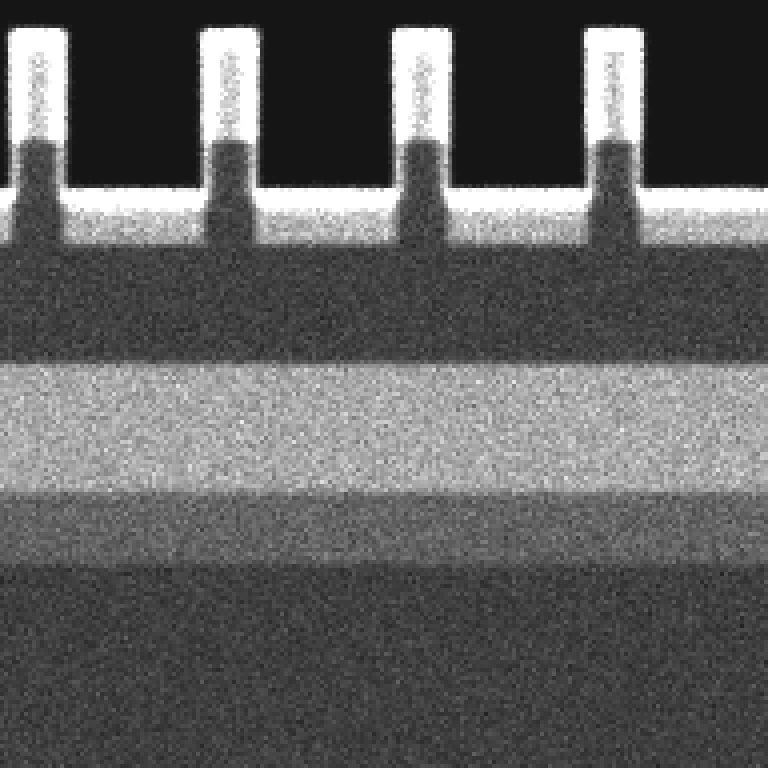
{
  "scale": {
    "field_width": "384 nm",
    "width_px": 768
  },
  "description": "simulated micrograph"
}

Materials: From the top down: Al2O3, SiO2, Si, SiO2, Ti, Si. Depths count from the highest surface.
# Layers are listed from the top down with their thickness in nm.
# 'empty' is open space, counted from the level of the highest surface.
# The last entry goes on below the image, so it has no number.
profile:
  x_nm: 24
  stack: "Al2O3 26, SiO2 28, Si 112, SiO2 64, Ti 36, Si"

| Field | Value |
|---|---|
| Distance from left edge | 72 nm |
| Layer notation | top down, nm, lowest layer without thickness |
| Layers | empty 80, Al2O3 26, Si 60, SiO2 64, Ti 36, Si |